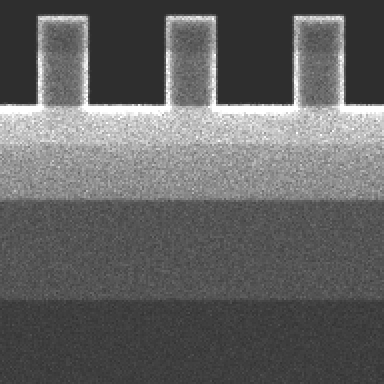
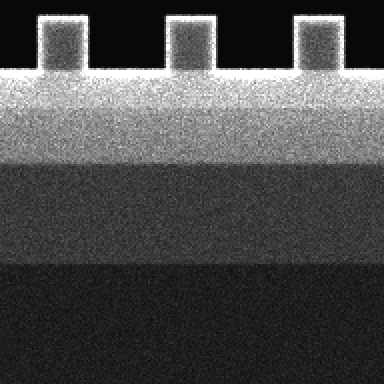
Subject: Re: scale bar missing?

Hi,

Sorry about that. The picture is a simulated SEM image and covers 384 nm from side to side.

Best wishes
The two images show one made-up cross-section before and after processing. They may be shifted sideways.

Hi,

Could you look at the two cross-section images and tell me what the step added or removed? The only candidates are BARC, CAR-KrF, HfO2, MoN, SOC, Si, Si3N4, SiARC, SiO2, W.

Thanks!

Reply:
removed SOC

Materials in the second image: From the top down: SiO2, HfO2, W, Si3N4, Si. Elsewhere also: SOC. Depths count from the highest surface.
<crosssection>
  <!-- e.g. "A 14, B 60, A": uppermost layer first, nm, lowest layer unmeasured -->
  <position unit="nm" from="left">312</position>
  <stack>SiO2 54, HfO2 38, W 56, Si3N4 100, Si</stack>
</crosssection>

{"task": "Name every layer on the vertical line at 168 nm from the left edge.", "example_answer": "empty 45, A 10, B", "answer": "SiO2 54, HfO2 38, W 56, Si3N4 100, Si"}